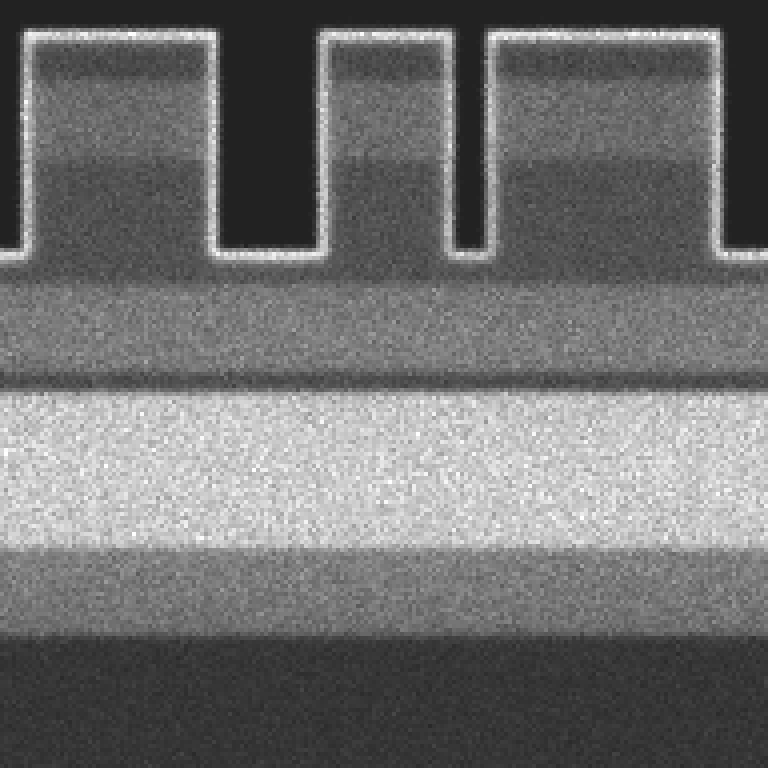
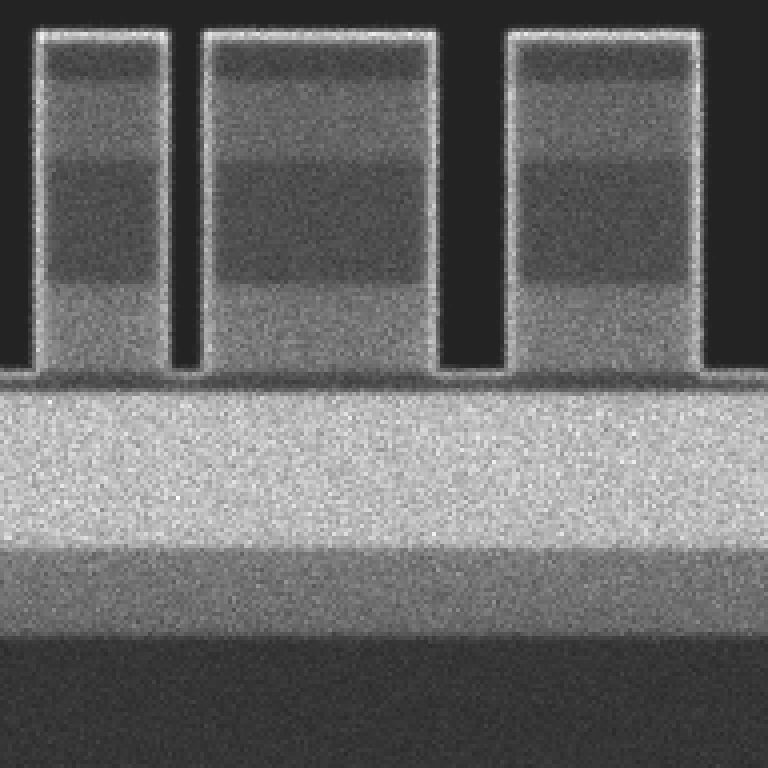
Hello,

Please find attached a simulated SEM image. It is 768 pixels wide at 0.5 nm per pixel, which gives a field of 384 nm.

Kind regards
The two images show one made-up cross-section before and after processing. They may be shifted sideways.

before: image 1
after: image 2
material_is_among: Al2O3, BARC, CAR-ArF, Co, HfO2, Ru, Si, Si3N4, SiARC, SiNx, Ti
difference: Ru and Si3N4, removed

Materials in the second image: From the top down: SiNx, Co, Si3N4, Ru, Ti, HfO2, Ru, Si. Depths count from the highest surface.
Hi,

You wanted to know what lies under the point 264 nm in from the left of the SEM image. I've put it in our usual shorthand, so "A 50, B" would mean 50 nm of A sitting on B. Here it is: SiNx 24, Co 40, Si3N4 62, Ru 44, Ti 10, HfO2 78, Ru 44, Si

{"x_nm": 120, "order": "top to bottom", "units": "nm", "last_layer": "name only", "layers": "SiNx 24, Co 40, Si3N4 62, Ru 44, Ti 10, HfO2 78, Ru 44, Si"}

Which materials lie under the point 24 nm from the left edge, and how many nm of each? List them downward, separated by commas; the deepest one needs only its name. SiNx 24, Co 40, Si3N4 62, Ru 44, Ti 10, HfO2 78, Ru 44, Si